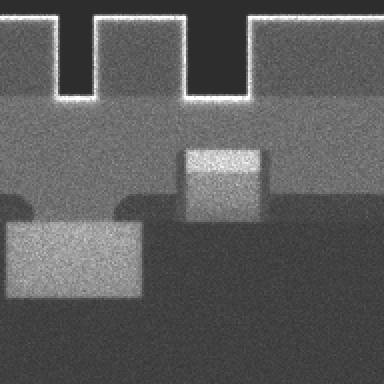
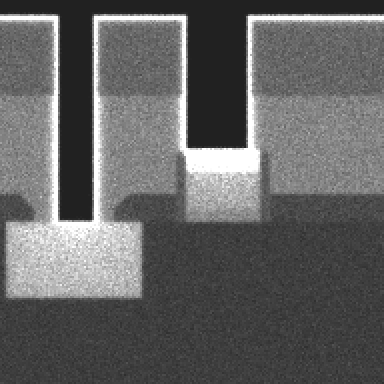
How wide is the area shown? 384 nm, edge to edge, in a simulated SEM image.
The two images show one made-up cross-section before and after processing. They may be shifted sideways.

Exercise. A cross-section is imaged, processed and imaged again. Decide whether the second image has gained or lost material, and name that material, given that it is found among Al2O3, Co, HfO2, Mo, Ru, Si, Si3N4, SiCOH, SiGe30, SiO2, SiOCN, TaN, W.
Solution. removed: SiO2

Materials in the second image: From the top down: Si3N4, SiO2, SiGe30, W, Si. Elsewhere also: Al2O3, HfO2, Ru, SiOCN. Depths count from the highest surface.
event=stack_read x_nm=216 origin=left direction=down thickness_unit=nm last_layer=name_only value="empty 134, HfO2 22, Ru 38, Al2O3 12, Si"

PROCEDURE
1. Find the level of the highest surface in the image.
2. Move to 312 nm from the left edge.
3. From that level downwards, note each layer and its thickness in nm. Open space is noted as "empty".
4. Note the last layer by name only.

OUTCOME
Si3N4 80, SiO2 98, SiGe30 28, Si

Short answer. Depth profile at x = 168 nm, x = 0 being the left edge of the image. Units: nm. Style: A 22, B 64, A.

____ Si3N4 80, SiO2 98, SiGe30 28, Si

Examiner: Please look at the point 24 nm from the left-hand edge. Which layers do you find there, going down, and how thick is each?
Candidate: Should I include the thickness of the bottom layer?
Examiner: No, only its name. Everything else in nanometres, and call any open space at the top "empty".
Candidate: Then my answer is Si3N4 80, SiO2 104, SiGe30 22, W 76, Si